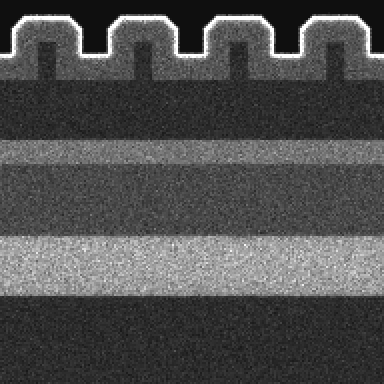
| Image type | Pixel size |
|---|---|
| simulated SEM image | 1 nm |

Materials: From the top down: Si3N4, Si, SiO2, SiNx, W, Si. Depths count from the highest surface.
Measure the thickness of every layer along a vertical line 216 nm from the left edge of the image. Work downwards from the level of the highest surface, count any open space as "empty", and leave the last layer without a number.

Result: Si3N4 64, Si 60, SiO2 24, SiNx 72, W 60, Si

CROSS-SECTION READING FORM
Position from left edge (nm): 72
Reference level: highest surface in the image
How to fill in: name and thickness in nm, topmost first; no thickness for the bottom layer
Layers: empty 4, Si3N4 60, Si 60, SiO2 24, SiNx 72, W 60, Si